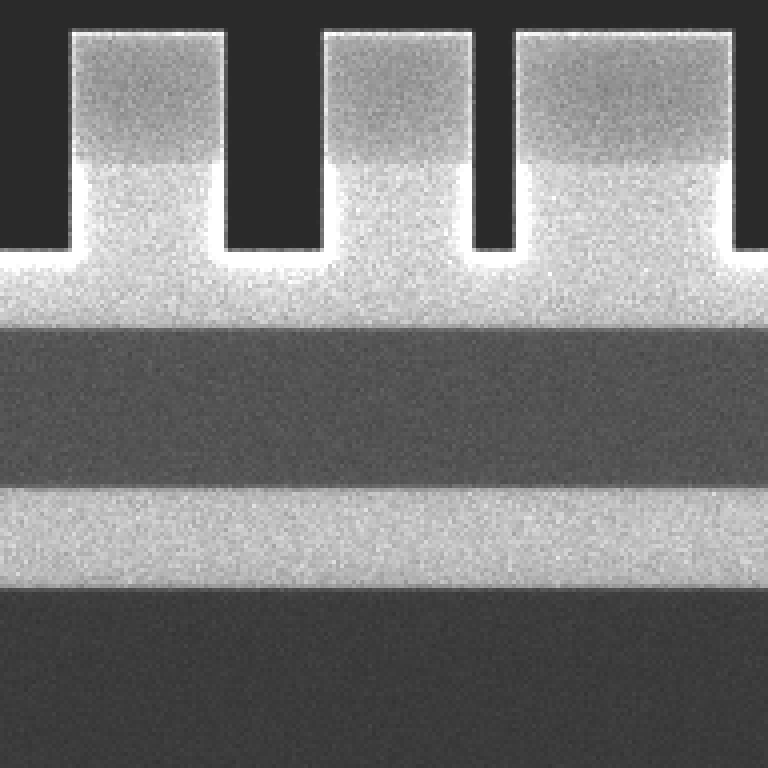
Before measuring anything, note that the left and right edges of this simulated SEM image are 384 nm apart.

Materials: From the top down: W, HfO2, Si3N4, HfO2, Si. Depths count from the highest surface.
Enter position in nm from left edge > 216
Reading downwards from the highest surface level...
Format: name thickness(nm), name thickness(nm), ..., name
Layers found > W 66, HfO2 82, Si3N4 80, HfO2 50, Si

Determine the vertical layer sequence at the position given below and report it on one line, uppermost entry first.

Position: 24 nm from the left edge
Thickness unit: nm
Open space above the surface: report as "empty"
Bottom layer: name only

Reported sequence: empty 110, HfO2 38, Si3N4 80, HfO2 50, Si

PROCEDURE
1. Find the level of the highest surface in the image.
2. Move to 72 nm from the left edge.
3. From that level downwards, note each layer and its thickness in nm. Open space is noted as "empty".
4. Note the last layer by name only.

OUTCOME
W 66, HfO2 82, Si3N4 80, HfO2 50, Si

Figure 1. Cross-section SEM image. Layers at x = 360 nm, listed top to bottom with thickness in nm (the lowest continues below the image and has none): W 66, HfO2 82, Si3N4 80, HfO2 50, Si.